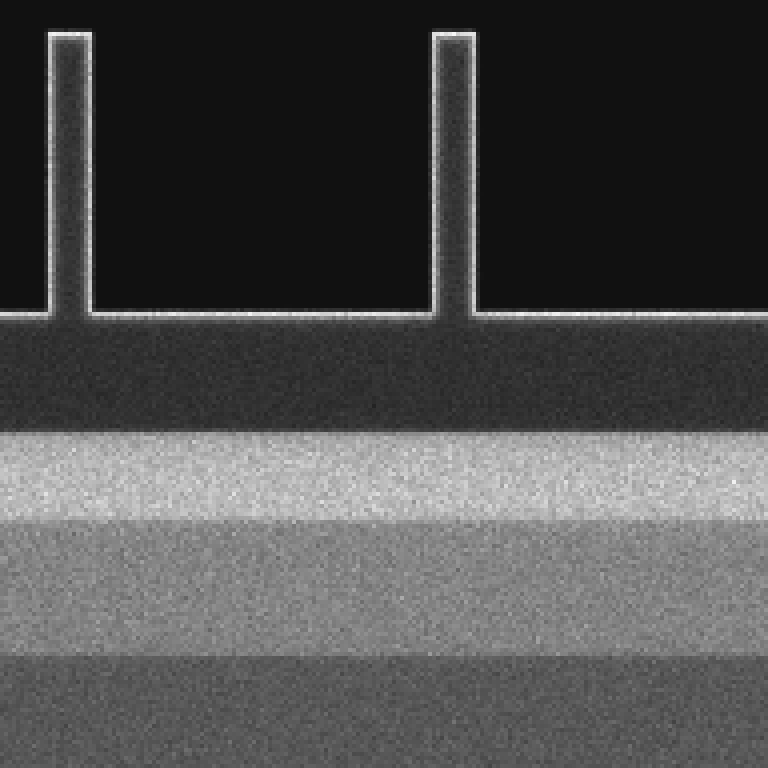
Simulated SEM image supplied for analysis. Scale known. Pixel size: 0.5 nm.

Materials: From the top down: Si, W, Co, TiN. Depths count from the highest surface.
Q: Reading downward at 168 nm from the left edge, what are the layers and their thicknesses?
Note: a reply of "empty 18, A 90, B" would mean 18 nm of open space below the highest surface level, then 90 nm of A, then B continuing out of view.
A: empty 140, Si 60, W 44, Co 68, TiN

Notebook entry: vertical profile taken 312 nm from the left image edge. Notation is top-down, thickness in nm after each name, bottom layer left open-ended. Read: empty 140, Si 60, W 44, Co 68, TiN